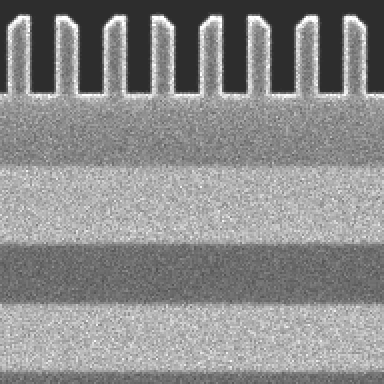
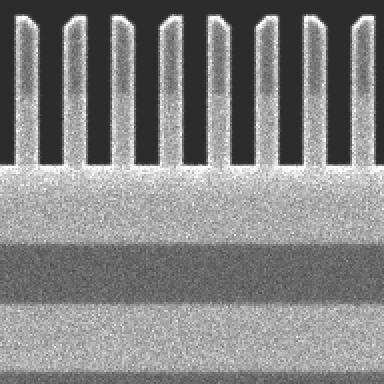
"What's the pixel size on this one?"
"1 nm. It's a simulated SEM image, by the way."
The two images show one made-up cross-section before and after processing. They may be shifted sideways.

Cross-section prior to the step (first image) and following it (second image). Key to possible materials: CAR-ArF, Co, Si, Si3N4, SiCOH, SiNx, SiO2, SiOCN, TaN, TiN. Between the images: TiN was removed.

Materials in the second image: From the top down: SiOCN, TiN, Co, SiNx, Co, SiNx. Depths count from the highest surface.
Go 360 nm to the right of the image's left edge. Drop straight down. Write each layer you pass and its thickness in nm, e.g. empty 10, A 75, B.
empty 2, SiOCN 76, TiN 72, Co 78, SiNx 60, Co 68, SiNx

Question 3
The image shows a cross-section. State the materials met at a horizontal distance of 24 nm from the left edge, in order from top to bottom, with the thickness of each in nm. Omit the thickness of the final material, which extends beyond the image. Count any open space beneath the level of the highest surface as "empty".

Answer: SiOCN 78, TiN 72, Co 78, SiNx 60, Co 68, SiNx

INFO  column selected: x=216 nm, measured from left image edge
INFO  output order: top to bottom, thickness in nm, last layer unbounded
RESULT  SiOCN 78, TiN 72, Co 78, SiNx 60, Co 68, SiNx